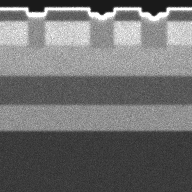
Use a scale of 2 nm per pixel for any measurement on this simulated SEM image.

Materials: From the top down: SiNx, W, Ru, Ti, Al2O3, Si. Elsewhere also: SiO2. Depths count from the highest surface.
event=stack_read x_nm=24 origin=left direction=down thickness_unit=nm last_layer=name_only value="SiNx 26, W 48, Ru 62, Ti 58, Al2O3 52, Si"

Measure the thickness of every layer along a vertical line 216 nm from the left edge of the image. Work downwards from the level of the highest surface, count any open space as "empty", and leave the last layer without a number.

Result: empty 10, SiO2 70, Ru 56, Ti 58, Al2O3 52, Si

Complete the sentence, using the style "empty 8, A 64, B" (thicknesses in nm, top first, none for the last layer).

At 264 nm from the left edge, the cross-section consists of SiNx 26, W 48, Ru 62, Ti 58, Al2O3 52, Si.